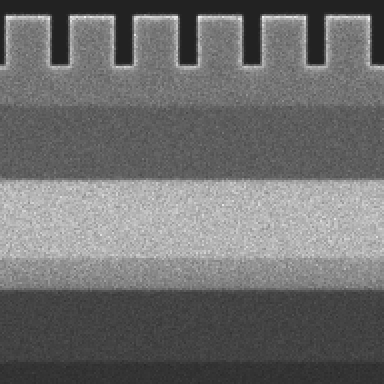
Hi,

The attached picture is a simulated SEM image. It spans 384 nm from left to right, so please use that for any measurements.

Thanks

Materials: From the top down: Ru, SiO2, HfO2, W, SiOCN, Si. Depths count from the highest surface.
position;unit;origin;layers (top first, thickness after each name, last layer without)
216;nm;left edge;Ru 90, SiO2 74, HfO2 78, W 32, SiOCN 72, Si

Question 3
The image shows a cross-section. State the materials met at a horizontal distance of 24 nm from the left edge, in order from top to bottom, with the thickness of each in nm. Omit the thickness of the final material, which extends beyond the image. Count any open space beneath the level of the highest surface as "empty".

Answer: Ru 90, SiO2 74, HfO2 78, W 32, SiOCN 72, Si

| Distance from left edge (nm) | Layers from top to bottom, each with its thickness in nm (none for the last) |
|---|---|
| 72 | Ru 90, SiO2 74, HfO2 78, W 32, SiOCN 72, Si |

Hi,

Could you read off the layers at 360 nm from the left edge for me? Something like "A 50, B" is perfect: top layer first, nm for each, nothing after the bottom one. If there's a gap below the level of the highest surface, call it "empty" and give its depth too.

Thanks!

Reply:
Ru 90, SiO2 74, HfO2 78, W 32, SiOCN 72, Si